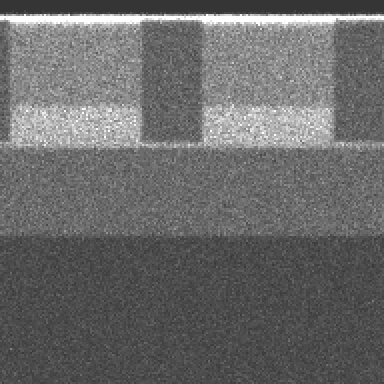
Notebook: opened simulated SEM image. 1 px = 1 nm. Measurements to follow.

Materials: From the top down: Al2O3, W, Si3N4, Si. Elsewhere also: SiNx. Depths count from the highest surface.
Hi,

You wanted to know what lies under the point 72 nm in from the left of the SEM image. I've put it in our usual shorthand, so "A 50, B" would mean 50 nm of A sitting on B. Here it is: Al2O3 90, W 42, Si3N4 88, Si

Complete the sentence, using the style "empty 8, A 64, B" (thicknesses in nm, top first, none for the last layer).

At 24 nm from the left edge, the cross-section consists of Al2O3 90, W 42, Si3N4 88, Si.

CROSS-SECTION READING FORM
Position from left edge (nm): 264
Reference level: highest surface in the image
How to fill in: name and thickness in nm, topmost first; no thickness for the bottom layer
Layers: Al2O3 90, W 42, Si3N4 88, Si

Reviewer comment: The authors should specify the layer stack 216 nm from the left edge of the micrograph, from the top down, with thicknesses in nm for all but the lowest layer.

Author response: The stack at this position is Al2O3 90, W 42, Si3N4 88, Si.